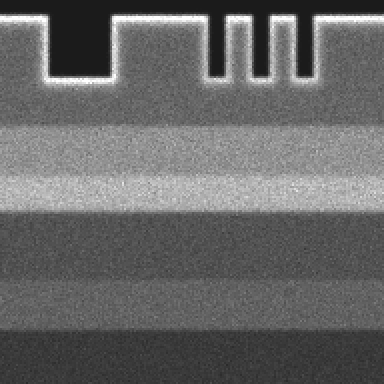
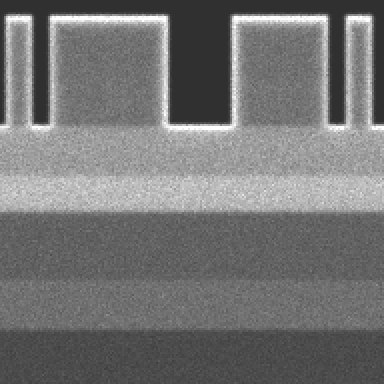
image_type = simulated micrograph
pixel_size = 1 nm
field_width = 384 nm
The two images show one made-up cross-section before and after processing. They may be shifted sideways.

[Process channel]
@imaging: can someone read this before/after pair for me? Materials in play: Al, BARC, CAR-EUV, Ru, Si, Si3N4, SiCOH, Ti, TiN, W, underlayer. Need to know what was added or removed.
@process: underlayer removed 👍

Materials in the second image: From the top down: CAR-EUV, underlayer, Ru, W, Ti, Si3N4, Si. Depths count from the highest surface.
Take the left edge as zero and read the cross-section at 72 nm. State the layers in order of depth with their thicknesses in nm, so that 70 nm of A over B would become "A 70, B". CAR-EUV 62, underlayer 48, Ru 50, W 36, Ti 68, Si3N4 50, Si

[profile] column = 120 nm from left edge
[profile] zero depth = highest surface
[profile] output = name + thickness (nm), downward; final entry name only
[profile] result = CAR-EUV 62, underlayer 48, Ru 50, W 36, Ti 68, Si3N4 50, Si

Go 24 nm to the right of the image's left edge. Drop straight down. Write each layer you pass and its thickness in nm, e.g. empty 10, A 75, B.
CAR-EUV 62, underlayer 48, Ru 50, W 36, Ti 68, Si3N4 50, Si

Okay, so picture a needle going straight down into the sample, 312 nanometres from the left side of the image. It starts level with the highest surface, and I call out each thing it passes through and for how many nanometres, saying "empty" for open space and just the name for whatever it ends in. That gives CAR-EUV 62, underlayer 48, Ru 50, W 36, Ti 68, Si3N4 50, Si